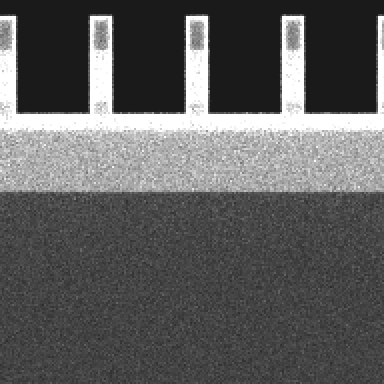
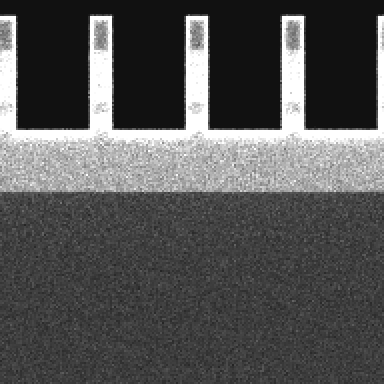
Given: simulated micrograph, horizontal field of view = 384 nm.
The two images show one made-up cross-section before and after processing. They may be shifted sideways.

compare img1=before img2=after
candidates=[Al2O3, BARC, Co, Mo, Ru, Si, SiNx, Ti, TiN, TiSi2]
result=removed:Ru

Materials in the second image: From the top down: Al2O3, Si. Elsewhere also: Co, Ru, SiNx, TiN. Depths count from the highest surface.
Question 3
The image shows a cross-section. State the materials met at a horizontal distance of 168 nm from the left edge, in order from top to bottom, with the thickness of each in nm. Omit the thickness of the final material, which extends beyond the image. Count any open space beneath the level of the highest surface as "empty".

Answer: empty 114, Al2O3 62, Si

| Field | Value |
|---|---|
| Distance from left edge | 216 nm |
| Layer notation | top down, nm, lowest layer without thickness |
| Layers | empty 114, Al2O3 62, Si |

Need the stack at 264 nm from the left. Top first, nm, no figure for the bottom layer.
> empty 114, Al2O3 62, Si